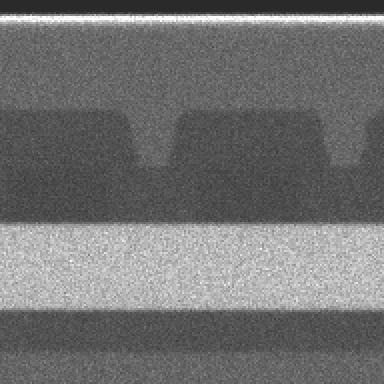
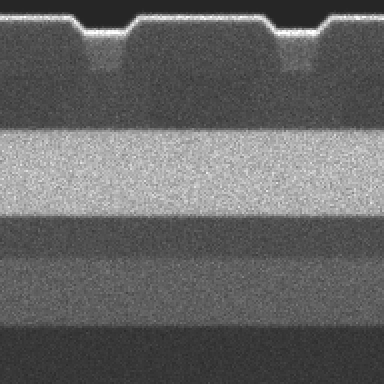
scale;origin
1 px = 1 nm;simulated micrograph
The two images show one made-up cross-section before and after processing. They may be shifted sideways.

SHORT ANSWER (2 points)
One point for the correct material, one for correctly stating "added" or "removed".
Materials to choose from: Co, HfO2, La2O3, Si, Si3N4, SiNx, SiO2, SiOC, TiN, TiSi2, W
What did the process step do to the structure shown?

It removed SiO2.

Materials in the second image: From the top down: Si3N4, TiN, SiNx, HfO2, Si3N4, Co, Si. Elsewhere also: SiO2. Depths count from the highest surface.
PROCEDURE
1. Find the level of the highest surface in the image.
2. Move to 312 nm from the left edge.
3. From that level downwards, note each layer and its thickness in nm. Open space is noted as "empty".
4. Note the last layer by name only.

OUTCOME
empty 14, SiO2 28, Si3N4 48, TiN 24, HfO2 86, Si3N4 42, Co 68, Si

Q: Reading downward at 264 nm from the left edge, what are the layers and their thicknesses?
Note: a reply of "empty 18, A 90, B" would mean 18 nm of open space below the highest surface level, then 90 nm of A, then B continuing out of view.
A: empty 2, Si3N4 34, TiN 78, HfO2 86, Si3N4 42, Co 68, Si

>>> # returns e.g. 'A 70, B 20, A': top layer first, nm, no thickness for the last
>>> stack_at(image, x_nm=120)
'empty 14, SiO2 28, Si3N4 48, TiN 24, HfO2 86, Si3N4 42, Co 68, Si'